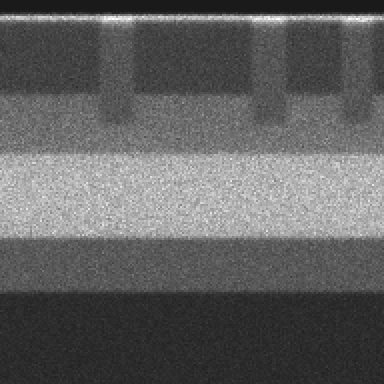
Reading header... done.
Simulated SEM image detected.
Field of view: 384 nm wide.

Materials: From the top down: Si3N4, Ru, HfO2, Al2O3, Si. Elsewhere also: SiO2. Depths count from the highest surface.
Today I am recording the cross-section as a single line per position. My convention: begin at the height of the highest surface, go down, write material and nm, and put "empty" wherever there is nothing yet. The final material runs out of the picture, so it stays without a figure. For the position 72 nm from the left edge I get Si3N4 78, Ru 60, HfO2 84, Al2O3 54, Si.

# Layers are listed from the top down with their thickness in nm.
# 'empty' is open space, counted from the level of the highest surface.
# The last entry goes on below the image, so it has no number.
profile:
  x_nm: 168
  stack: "Si3N4 78, Ru 60, HfO2 84, Al2O3 54, Si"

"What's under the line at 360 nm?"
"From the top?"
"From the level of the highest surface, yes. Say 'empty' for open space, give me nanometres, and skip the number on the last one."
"SiO2 108, Ru 30, HfO2 84, Al2O3 54, Si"